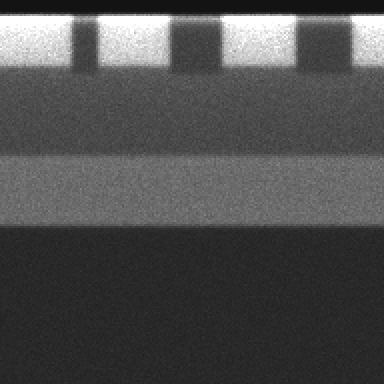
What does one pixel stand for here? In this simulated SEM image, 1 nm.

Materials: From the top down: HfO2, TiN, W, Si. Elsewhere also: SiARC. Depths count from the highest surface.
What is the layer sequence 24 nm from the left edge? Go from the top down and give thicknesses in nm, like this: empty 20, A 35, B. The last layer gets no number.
HfO2 50, TiN 90, W 70, Si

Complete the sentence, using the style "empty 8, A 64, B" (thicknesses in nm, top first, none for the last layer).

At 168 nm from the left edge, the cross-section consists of HfO2 50, TiN 90, W 70, Si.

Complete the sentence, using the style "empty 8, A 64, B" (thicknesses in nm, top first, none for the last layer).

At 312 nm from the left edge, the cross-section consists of SiARC 58, TiN 82, W 70, Si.